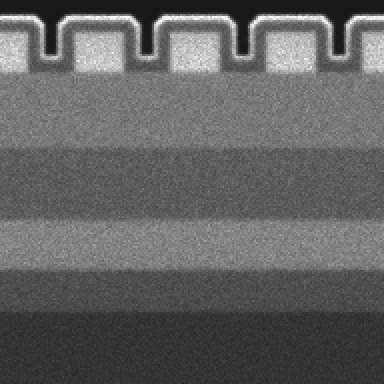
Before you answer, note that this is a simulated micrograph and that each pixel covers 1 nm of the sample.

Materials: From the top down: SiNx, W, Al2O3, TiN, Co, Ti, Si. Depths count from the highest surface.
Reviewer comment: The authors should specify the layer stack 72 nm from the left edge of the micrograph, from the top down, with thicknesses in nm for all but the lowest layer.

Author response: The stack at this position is SiNx 56, Al2O3 76, TiN 72, Co 50, Ti 42, Si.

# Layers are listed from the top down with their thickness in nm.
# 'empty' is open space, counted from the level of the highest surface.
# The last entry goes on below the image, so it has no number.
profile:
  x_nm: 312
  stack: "SiNx 16, W 40, Al2O3 76, TiN 72, Co 50, Ti 42, Si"